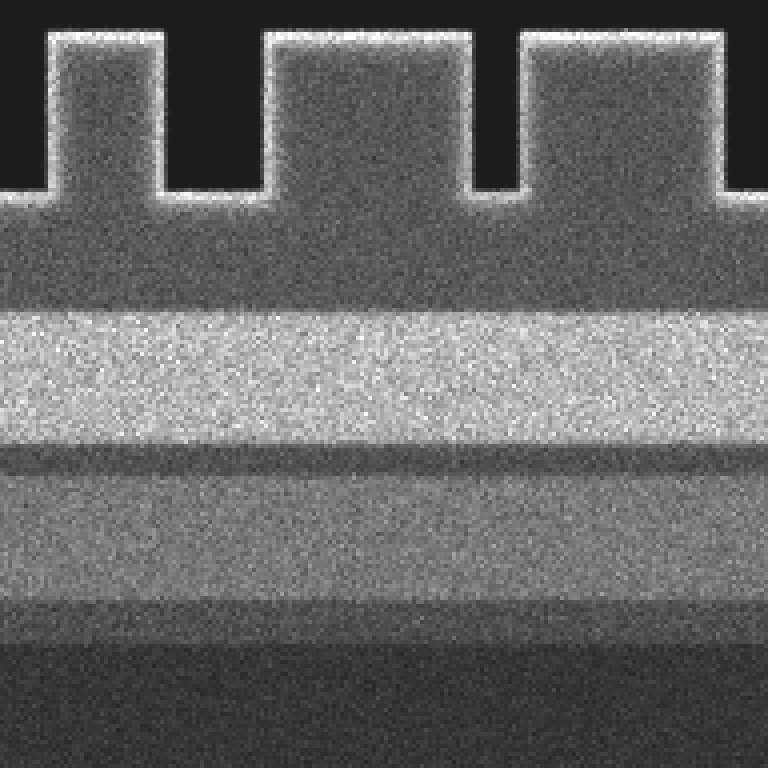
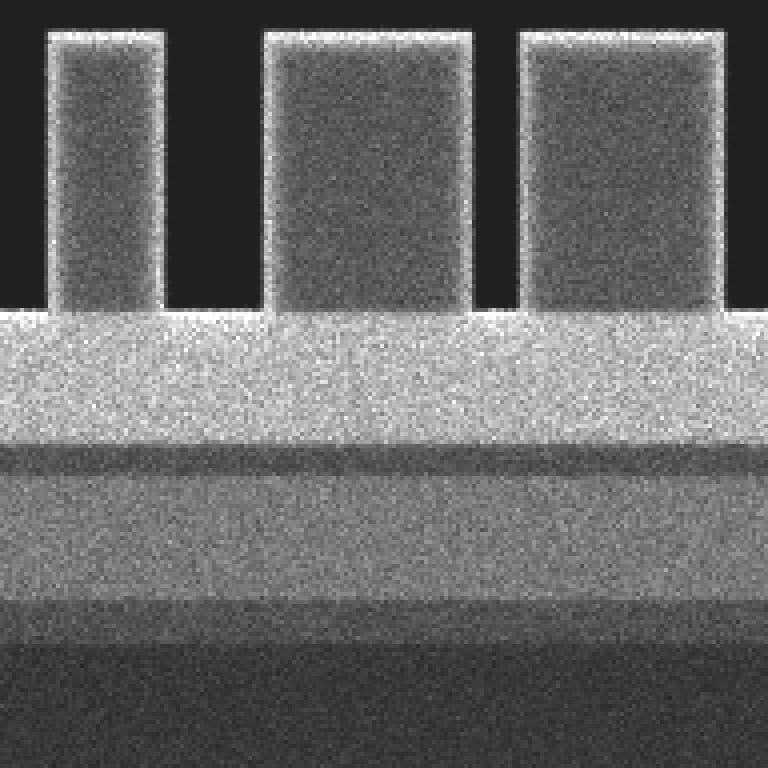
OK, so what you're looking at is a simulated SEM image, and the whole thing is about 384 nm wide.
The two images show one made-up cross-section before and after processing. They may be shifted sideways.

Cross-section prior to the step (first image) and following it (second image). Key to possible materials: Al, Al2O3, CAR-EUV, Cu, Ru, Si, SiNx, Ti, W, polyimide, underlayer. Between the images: underlayer was removed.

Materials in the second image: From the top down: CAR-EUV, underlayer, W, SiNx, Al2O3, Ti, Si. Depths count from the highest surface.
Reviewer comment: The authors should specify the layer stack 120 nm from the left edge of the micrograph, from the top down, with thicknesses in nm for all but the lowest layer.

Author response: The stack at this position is empty 140, W 66, SiNx 16, Al2O3 62, Ti 22, Si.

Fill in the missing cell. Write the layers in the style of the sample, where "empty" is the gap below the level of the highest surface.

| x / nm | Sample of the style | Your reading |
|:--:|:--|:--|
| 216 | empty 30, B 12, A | CAR-EUV 80, underlayer 60, W 66, SiNx 16, Al2O3 62, Ti 22, Si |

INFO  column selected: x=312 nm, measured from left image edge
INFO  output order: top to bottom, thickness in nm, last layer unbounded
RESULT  CAR-EUV 80, underlayer 60, W 66, SiNx 16, Al2O3 62, Ti 22, Si